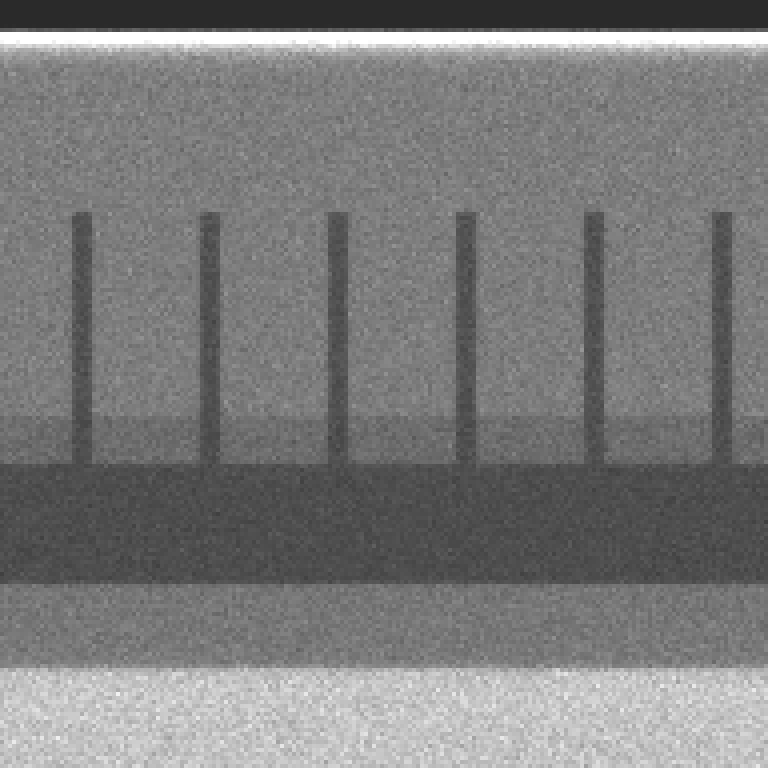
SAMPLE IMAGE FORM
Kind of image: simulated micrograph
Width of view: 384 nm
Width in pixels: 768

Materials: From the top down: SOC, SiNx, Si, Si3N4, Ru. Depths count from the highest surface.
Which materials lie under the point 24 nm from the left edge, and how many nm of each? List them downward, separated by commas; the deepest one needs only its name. SOC 192, SiNx 24, Si 60, Si3N4 42, Ru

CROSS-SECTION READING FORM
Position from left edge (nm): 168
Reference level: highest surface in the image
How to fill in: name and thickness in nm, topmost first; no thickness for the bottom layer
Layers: SOC 90, Si 186, Si3N4 42, Ru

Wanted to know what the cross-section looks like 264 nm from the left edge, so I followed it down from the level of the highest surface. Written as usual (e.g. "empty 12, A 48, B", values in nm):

SOC 192, SiNx 24, Si 60, Si3N4 42, Ru